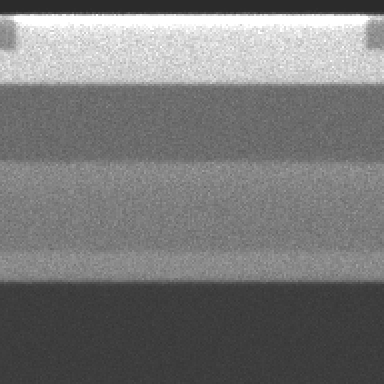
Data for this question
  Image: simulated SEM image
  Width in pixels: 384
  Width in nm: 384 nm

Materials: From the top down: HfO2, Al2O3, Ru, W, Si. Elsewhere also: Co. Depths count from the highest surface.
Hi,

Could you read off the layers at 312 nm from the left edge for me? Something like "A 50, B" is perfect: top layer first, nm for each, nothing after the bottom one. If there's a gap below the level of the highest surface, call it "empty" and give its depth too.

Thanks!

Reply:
HfO2 68, Al2O3 78, Ru 90, W 30, Si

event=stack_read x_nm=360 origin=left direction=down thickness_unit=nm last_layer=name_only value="HfO2 68, Al2O3 78, Ru 90, W 30, Si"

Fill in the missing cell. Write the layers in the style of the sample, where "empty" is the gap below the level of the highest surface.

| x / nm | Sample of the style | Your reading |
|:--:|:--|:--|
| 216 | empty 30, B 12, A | HfO2 68, Al2O3 78, Ru 90, W 30, Si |